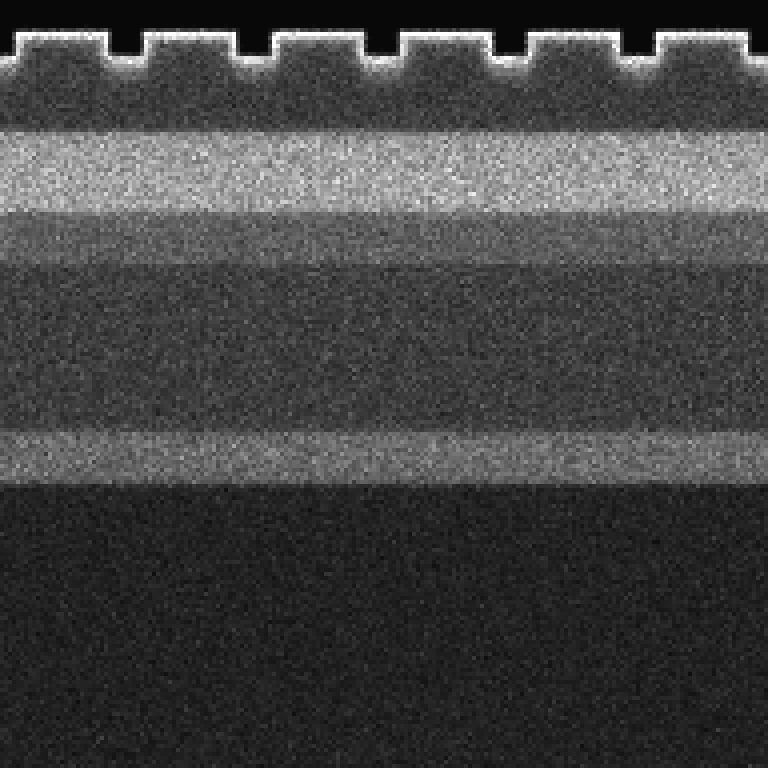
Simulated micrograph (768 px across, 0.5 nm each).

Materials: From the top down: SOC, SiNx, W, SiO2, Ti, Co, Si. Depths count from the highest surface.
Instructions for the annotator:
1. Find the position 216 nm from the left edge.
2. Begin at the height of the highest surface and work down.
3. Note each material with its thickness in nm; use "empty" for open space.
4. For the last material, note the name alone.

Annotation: SiNx 50, W 40, SiO2 26, Ti 84, Co 26, Si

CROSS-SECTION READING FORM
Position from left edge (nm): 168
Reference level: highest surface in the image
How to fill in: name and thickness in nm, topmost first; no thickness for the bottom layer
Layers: SiNx 50, W 40, SiO2 26, Ti 84, Co 26, Si